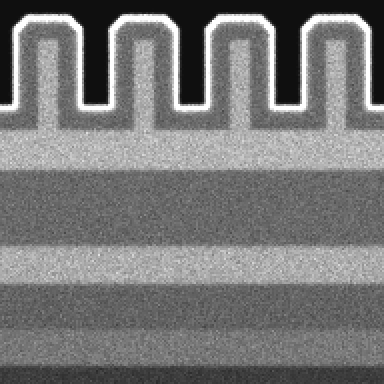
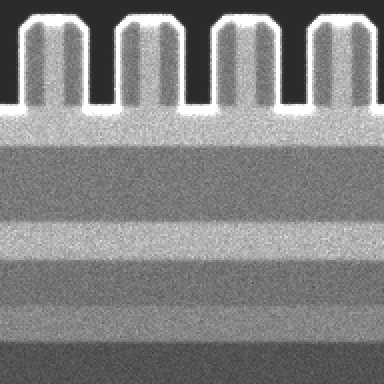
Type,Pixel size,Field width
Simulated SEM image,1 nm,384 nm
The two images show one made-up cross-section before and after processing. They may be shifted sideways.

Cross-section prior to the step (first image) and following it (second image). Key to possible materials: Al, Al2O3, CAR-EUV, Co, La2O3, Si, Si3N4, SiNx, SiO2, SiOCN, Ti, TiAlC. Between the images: SiOCN was removed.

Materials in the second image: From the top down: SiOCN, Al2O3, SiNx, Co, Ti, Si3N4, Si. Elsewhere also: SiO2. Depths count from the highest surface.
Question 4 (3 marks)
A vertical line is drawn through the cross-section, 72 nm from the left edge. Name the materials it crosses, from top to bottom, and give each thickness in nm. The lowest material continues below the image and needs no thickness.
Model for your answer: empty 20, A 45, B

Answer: SiOCN 90, Al2O3 40, SiNx 76, Co 38, Ti 46, Si3N4 36, Si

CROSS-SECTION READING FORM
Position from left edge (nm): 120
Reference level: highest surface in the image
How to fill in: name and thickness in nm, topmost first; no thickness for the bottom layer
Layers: empty 8, SiOCN 82, Al2O3 40, SiNx 76, Co 38, Ti 46, Si3N4 36, Si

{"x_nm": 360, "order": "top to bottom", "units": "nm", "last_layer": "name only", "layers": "SiOCN 90, Al2O3 40, SiNx 76, Co 38, Ti 46, Si3N4 36, Si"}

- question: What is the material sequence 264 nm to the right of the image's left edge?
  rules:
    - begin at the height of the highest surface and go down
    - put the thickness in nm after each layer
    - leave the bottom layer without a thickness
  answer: SiOCN 90, Al2O3 40, SiNx 76, Co 38, Ti 46, Si3N4 36, Si